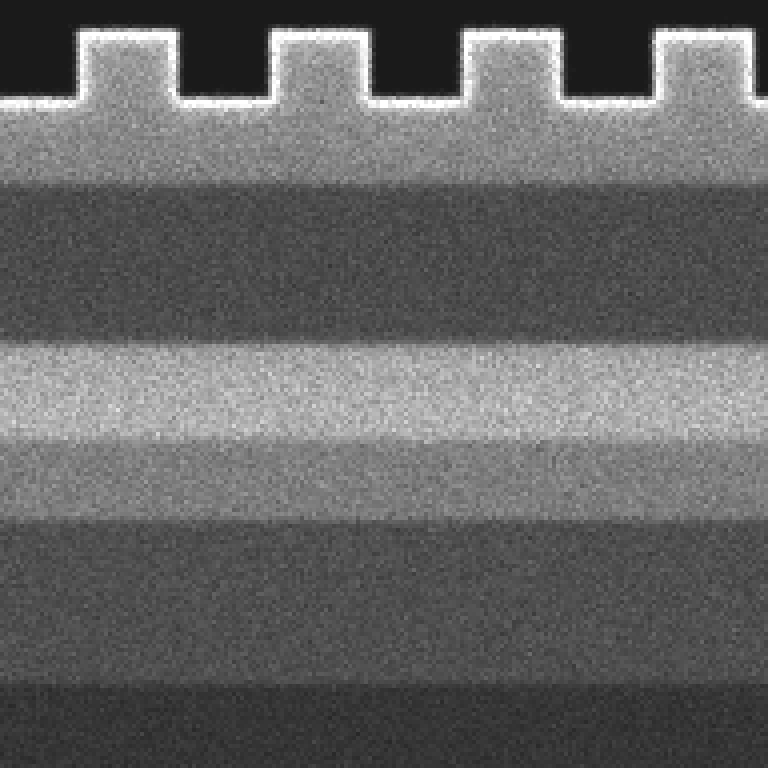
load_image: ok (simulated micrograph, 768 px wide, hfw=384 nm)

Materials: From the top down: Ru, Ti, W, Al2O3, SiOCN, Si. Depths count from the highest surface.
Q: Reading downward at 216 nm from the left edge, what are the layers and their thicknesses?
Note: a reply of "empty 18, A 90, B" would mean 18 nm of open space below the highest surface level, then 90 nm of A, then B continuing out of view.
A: empty 34, Ru 42, Ti 80, W 48, Al2O3 40, SiOCN 82, Si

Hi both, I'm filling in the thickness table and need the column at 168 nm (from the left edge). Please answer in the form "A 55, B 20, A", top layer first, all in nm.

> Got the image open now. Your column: Ru 76, Ti 80, W 48, Al2O3 40, SiOCN 82, Si